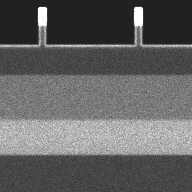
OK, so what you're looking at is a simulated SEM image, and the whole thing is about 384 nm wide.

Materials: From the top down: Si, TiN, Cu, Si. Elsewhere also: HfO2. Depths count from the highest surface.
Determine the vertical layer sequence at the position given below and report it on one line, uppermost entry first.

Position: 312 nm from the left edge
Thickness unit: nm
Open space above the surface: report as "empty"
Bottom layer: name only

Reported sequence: empty 74, Si 60, TiN 90, Cu 70, Si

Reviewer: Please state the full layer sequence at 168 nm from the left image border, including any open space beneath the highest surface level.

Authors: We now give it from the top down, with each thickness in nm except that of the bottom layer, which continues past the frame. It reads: empty 74, Si 60, TiN 90, Cu 70, Si